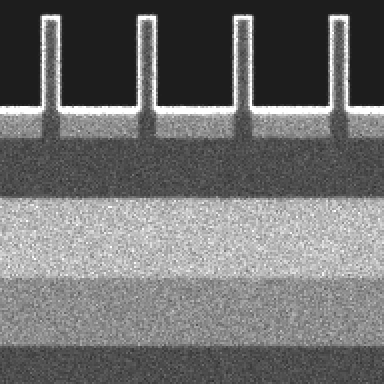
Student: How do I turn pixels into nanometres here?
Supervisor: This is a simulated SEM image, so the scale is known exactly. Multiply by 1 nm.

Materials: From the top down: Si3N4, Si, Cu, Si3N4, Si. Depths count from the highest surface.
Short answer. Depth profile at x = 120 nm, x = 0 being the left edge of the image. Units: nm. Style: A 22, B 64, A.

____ empty 92, Si3N4 30, Si 60, Cu 80, Si3N4 68, Si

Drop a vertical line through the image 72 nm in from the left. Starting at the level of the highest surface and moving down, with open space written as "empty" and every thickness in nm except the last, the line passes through empty 92, Si3N4 30, Si 60, Cu 80, Si3N4 68, Si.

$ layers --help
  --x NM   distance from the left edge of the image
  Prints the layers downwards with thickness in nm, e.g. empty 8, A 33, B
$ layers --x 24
empty 92, Si3N4 30, Si 60, Cu 80, Si3N4 68, Si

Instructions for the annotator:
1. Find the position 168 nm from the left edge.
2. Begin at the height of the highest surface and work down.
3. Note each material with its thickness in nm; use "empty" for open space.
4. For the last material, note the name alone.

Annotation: empty 92, Si3N4 30, Si 60, Cu 80, Si3N4 68, Si